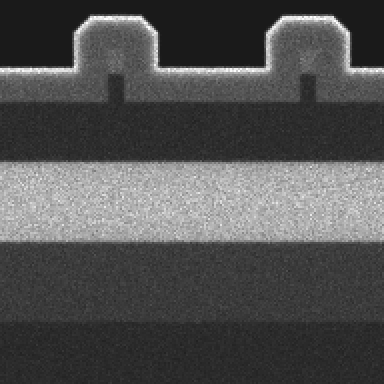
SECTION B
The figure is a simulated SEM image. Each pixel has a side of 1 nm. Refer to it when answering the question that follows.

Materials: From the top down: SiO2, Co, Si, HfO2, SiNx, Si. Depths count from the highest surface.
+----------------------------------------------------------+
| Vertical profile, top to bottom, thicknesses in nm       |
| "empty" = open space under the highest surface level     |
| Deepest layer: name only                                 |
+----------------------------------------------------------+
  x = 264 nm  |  empty 52, SiO2 34, Si 60, HfO2 80, SiNx 80, Si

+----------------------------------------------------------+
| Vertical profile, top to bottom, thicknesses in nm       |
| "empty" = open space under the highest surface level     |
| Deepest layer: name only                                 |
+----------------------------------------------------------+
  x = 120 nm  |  SiO2 34, Co 24, Si 88, HfO2 80, SiNx 80, Si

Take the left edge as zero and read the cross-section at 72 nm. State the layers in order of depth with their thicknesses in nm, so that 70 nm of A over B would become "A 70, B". empty 52, SiO2 34, Si 60, HfO2 80, SiNx 80, Si